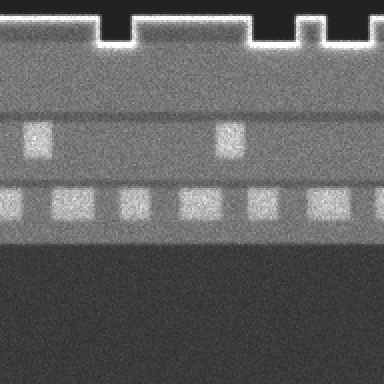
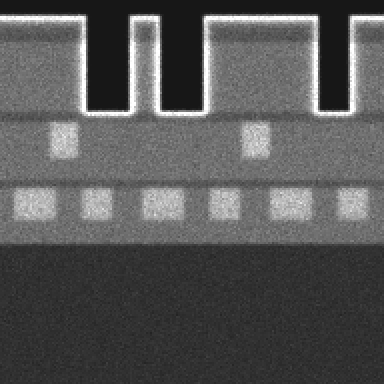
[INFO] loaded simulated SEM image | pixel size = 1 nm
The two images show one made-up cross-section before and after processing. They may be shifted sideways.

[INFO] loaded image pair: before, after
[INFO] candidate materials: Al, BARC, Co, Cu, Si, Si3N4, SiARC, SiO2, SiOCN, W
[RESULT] removed SiO2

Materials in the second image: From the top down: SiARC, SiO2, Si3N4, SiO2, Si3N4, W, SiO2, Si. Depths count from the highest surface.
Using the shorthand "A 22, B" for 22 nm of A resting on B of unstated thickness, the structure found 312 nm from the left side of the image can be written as SiARC 26, SiO2 70, Si3N4 10, SiO2 58, Si3N4 8, SiO2 56, Si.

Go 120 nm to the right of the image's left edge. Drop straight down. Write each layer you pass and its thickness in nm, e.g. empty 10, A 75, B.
empty 96, Si3N4 10, SiO2 58, Si3N4 8, SiO2 56, Si